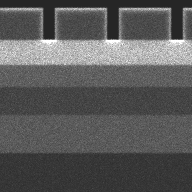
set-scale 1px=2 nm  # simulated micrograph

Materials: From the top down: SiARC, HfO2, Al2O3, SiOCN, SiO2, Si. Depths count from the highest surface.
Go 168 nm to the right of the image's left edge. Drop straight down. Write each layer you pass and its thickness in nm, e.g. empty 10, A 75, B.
SiARC 64, HfO2 50, Al2O3 44, SiOCN 56, SiO2 76, Si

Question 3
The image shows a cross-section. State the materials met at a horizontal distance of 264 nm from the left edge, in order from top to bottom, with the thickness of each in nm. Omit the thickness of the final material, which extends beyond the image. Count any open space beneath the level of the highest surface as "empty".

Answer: SiARC 64, HfO2 50, Al2O3 44, SiOCN 56, SiO2 76, Si